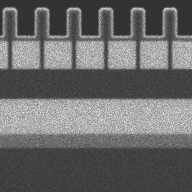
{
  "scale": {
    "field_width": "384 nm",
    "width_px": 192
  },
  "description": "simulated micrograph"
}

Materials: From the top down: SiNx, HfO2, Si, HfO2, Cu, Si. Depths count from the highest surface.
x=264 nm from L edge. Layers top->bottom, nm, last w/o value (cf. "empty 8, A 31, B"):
empty 2, SiNx 64, HfO2 56, Si 60, HfO2 70, Cu 28, Si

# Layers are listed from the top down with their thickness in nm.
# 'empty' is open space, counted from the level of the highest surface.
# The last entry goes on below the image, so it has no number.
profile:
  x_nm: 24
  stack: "SiNx 66, HfO2 56, Si 60, HfO2 70, Cu 28, Si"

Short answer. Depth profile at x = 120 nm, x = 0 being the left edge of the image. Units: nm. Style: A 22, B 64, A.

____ empty 56, SiNx 10, HfO2 56, Si 60, HfO2 70, Cu 28, Si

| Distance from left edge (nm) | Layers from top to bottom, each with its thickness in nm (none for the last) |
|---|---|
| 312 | empty 56, SiNx 10, HfO2 56, Si 60, HfO2 70, Cu 28, Si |